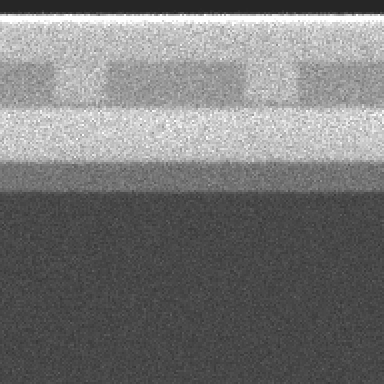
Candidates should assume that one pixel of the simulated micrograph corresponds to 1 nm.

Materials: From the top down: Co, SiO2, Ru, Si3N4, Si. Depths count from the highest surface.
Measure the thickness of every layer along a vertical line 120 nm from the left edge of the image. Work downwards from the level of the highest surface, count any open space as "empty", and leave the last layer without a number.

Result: Co 46, SiO2 46, Ru 54, Si3N4 30, Si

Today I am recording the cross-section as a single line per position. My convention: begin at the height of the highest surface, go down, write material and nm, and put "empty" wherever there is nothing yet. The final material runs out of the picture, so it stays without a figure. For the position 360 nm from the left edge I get Co 46, SiO2 46, Ru 54, Si3N4 30, Si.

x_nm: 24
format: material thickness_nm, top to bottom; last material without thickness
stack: Co 46, SiO2 46, Ru 54, Si3N4 30, Si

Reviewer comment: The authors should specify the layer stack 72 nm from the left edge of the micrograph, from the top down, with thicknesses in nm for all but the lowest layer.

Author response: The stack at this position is Co 86, SiO2 6, Ru 54, Si3N4 30, Si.